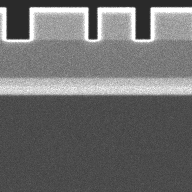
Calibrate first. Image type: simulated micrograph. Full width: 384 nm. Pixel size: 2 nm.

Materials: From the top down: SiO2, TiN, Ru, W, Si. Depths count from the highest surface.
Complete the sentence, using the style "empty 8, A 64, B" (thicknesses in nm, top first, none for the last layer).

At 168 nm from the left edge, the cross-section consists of SiO2 64, TiN 76, Ru 16, W 18, Si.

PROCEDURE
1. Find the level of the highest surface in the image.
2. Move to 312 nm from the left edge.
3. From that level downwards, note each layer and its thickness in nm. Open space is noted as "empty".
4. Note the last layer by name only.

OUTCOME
SiO2 64, TiN 76, Ru 16, W 18, Si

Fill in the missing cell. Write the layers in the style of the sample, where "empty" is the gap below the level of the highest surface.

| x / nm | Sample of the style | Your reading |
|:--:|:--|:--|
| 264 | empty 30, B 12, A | SiO2 64, TiN 76, Ru 16, W 18, Si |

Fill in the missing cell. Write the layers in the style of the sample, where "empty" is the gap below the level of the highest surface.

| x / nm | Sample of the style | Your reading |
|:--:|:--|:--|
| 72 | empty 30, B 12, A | SiO2 64, TiN 76, Ru 16, W 18, Si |